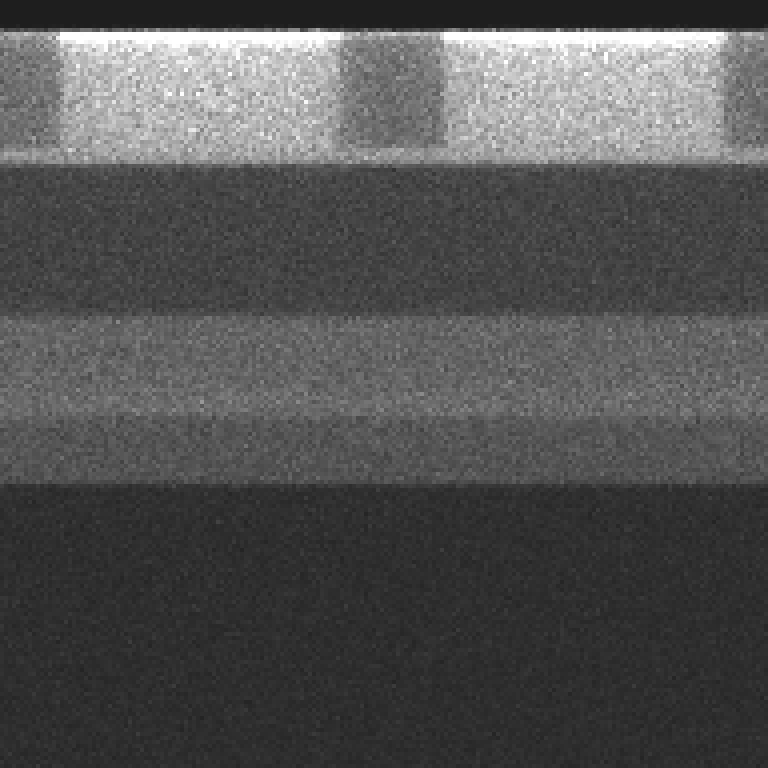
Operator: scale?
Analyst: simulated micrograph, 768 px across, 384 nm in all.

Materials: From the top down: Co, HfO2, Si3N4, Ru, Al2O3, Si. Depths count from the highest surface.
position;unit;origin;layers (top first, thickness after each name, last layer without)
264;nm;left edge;HfO2 66, Si3N4 76, Ru 50, Al2O3 34, Si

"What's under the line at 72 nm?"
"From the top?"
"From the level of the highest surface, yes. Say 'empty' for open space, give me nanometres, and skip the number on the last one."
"HfO2 66, Si3N4 76, Ru 50, Al2O3 34, Si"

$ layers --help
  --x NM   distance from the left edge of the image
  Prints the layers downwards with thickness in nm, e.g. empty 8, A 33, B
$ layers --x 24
Co 58, HfO2 8, Si3N4 76, Ru 50, Al2O3 34, Si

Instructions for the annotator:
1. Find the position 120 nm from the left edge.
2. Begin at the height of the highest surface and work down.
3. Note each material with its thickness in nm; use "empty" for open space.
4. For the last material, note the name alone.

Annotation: HfO2 66, Si3N4 76, Ru 50, Al2O3 34, Si